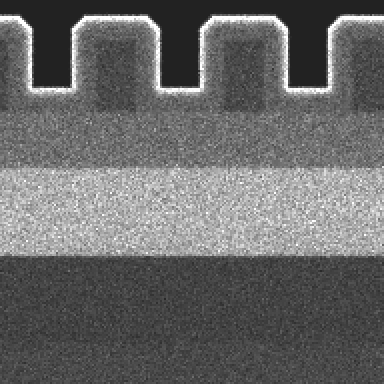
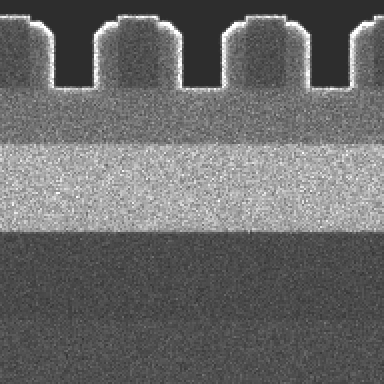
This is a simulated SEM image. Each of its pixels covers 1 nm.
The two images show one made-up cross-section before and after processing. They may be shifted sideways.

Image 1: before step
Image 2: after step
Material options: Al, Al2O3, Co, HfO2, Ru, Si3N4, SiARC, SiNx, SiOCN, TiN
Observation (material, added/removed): Al2O3, removed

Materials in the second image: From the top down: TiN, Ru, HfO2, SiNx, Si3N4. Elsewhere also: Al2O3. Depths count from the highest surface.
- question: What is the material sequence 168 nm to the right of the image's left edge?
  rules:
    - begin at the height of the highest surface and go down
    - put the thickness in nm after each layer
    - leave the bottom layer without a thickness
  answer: empty 6, Al2O3 66, Ru 56, HfO2 88, SiNx 88, Si3N4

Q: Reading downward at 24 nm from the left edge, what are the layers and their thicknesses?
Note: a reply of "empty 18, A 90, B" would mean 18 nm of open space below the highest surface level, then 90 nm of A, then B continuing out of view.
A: TiN 72, Ru 56, HfO2 88, SiNx 88, Si3N4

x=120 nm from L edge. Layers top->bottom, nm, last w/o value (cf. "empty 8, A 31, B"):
TiN 72, Ru 56, HfO2 88, SiNx 88, Si3N4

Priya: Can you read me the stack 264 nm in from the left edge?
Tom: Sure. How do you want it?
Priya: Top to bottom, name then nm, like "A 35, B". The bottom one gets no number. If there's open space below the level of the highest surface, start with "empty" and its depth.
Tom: TiN 72, Ru 56, HfO2 88, SiNx 88, Si3N4